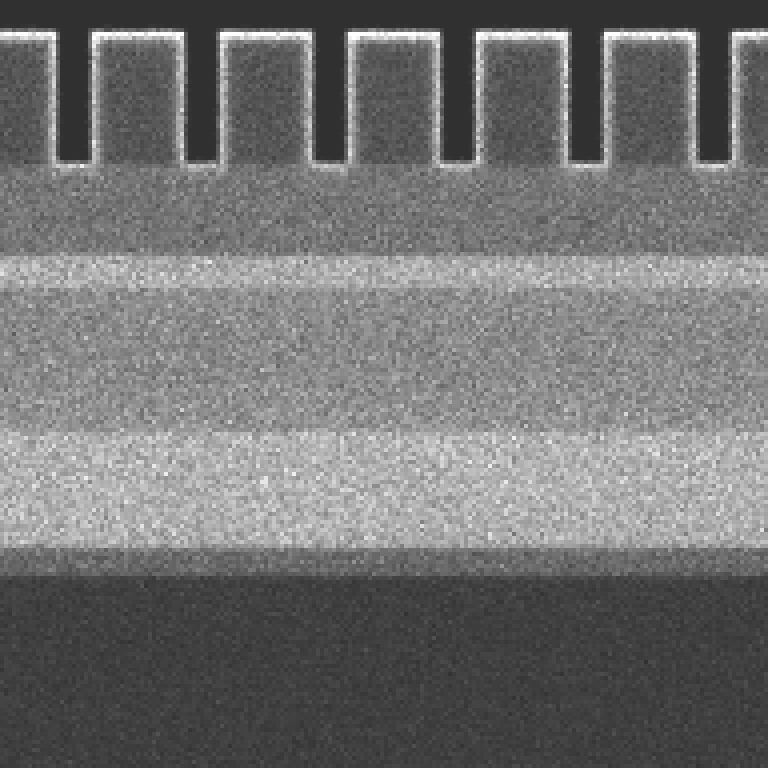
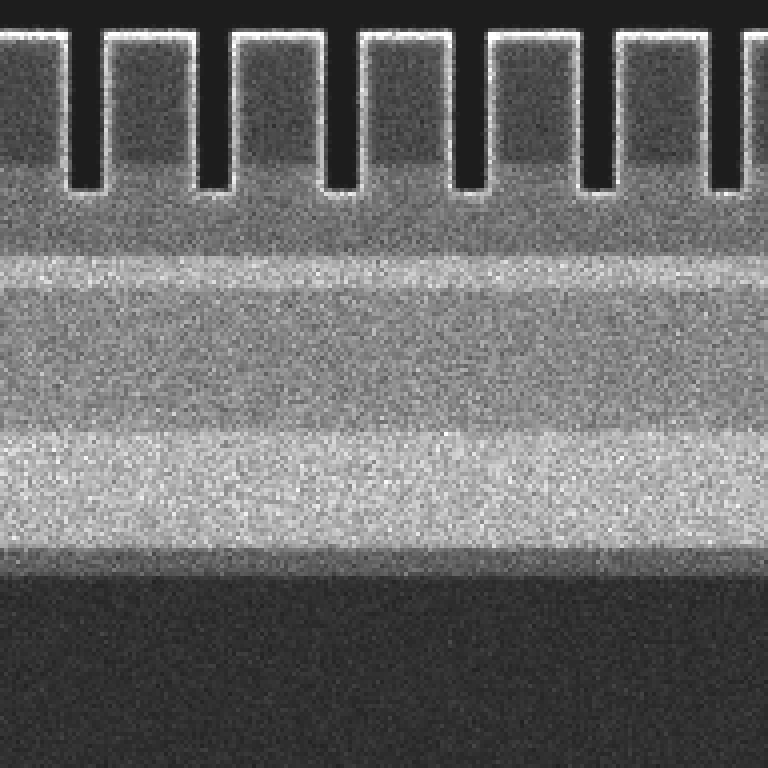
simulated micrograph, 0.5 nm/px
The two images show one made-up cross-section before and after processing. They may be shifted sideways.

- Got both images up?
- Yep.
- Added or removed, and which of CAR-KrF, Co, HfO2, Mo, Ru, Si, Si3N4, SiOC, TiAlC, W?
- removed, Ru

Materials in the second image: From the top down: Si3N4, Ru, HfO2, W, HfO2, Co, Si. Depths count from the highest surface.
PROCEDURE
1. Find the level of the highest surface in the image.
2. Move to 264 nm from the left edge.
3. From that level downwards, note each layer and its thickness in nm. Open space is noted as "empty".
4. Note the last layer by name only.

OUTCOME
Si3N4 66, Ru 46, HfO2 16, W 72, HfO2 58, Co 14, Si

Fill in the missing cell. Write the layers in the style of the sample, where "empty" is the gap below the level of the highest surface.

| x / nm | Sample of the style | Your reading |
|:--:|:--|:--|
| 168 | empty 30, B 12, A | empty 80, Ru 32, HfO2 16, W 72, HfO2 58, Co 14, Si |